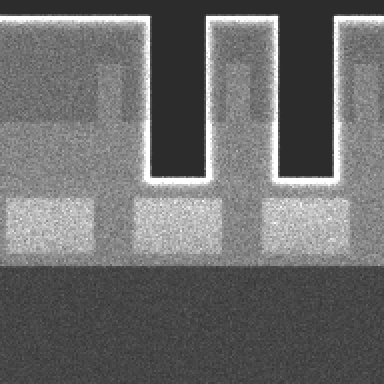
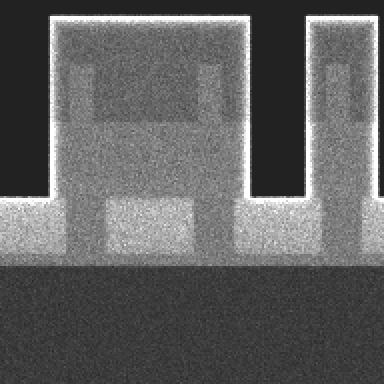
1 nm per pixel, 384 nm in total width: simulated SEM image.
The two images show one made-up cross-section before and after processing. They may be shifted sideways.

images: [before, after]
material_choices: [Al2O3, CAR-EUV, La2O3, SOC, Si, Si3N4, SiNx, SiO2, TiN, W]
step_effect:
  removed: Al2O3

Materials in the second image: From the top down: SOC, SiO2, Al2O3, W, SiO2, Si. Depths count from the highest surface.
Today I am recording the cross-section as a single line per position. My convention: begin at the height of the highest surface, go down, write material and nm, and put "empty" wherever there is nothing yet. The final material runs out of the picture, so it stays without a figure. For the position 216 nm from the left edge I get SOC 48, SiO2 114, Al2O3 20, SiO2 68, Si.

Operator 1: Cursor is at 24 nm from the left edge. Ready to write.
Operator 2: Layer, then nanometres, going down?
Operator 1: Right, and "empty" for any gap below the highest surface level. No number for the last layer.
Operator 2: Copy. empty 182, W 56, SiO2 12, Si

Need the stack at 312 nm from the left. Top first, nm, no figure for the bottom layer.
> SOC 106, SiO2 56, Al2O3 20, W 56, SiO2 12, Si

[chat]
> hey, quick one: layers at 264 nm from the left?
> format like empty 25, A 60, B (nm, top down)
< empty 182, W 56, SiO2 12, Si